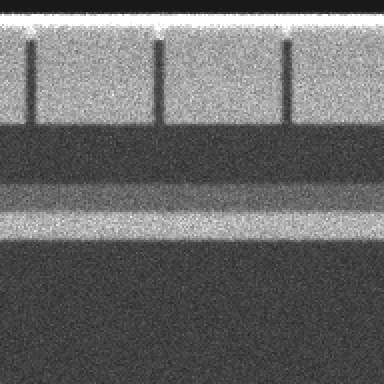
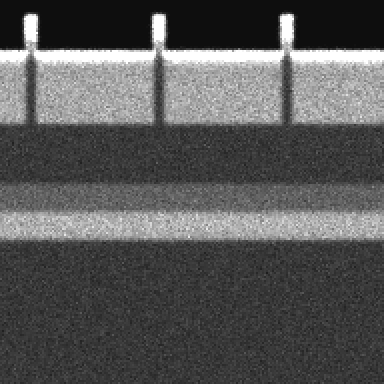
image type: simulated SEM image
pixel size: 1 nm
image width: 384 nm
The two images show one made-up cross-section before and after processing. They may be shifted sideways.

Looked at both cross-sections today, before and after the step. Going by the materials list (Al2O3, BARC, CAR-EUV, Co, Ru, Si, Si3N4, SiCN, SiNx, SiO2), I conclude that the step removed SiO2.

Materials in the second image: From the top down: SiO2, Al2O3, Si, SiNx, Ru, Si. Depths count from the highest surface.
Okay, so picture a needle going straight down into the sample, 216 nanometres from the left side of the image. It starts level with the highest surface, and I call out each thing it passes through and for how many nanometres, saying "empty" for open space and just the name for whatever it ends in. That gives empty 36, SiO2 28, Al2O3 44, Si 60, SiNx 28, Ru 28, Si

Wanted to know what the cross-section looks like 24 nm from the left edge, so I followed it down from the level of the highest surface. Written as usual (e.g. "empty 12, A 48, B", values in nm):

empty 36, SiO2 28, Al2O3 44, Si 60, SiNx 28, Ru 28, Si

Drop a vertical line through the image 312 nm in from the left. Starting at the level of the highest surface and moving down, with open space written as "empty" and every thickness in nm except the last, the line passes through empty 36, SiO2 28, Al2O3 44, Si 60, SiNx 28, Ru 28, Si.